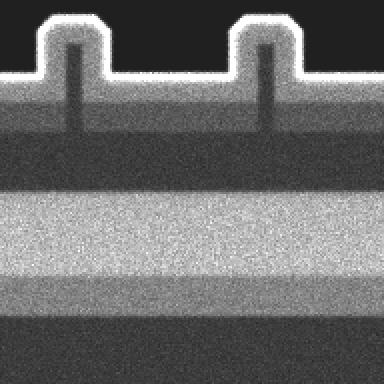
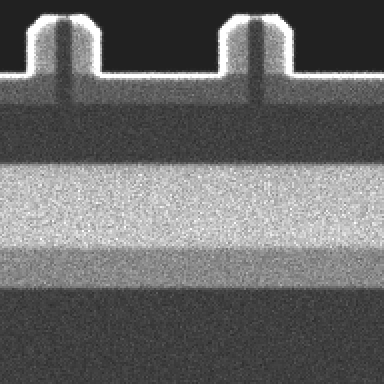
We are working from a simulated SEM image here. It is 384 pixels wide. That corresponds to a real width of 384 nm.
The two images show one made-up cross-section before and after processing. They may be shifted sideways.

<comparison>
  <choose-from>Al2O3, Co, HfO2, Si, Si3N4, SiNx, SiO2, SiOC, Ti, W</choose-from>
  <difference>Al2O3 removed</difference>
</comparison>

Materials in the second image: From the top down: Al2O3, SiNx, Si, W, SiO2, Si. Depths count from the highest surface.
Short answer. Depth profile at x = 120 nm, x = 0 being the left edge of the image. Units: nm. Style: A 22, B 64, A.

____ empty 58, SiNx 30, Si 60, W 84, SiO2 40, Si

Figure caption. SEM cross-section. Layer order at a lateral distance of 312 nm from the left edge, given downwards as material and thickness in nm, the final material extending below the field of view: empty 58, SiNx 30, Si 60, W 84, SiO2 40, Si